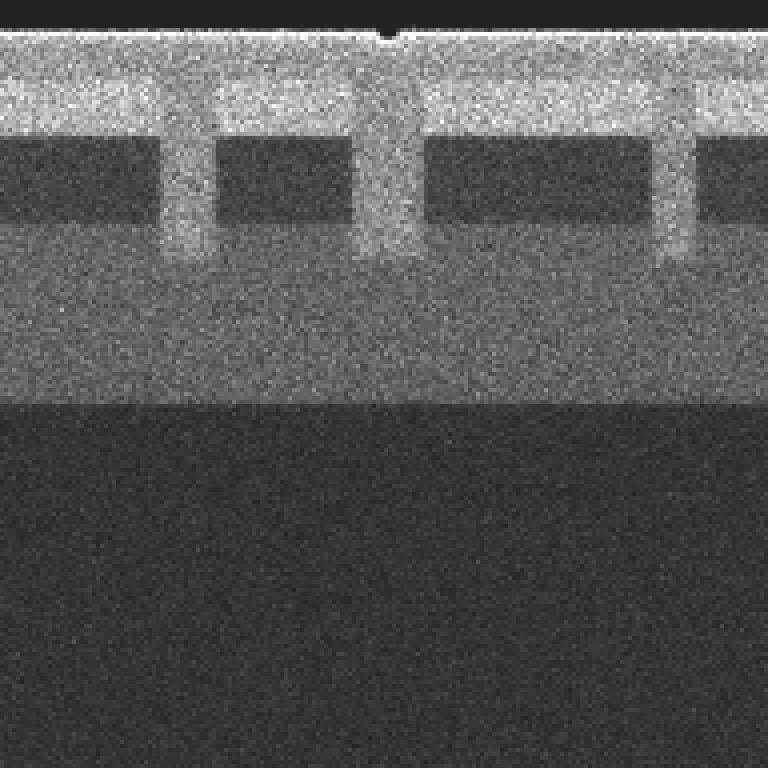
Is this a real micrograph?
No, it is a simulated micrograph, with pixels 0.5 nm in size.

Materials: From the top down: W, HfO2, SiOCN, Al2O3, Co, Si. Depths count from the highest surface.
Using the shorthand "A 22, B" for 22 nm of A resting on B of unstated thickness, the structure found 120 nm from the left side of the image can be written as W 24, HfO2 28, SiOCN 44, Al2O3 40, Co 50, Si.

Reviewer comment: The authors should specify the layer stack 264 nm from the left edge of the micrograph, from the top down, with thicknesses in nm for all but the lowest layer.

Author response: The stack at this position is W 24, HfO2 28, SiOCN 44, Al2O3 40, Co 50, Si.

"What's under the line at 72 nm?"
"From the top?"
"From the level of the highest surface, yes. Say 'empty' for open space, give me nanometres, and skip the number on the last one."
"W 24, HfO2 28, SiOCN 44, Al2O3 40, Co 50, Si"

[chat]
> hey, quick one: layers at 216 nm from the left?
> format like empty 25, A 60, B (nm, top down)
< W 24, HfO2 28, SiOCN 44, Al2O3 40, Co 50, Si